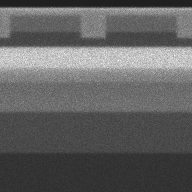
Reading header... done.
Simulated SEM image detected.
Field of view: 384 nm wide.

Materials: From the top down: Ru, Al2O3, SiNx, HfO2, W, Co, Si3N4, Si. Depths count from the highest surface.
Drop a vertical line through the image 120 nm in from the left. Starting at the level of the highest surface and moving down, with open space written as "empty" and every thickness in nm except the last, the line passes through Ru 14, Al2O3 34, SiNx 30, HfO2 42, W 28, Co 60, Si3N4 82, Si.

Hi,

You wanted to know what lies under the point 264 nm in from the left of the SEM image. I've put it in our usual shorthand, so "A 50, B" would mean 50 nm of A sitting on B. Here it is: Ru 14, Al2O3 34, SiNx 30, HfO2 42, W 28, Co 60, Si3N4 82, Si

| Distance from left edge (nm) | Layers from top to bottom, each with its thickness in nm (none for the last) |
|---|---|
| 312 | Ru 14, Al2O3 34, SiNx 30, HfO2 42, W 28, Co 60, Si3N4 82, Si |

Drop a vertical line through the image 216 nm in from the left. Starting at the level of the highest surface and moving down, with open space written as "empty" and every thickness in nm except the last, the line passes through Ru 14, Al2O3 34, SiNx 30, HfO2 42, W 28, Co 60, Si3N4 82, Si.